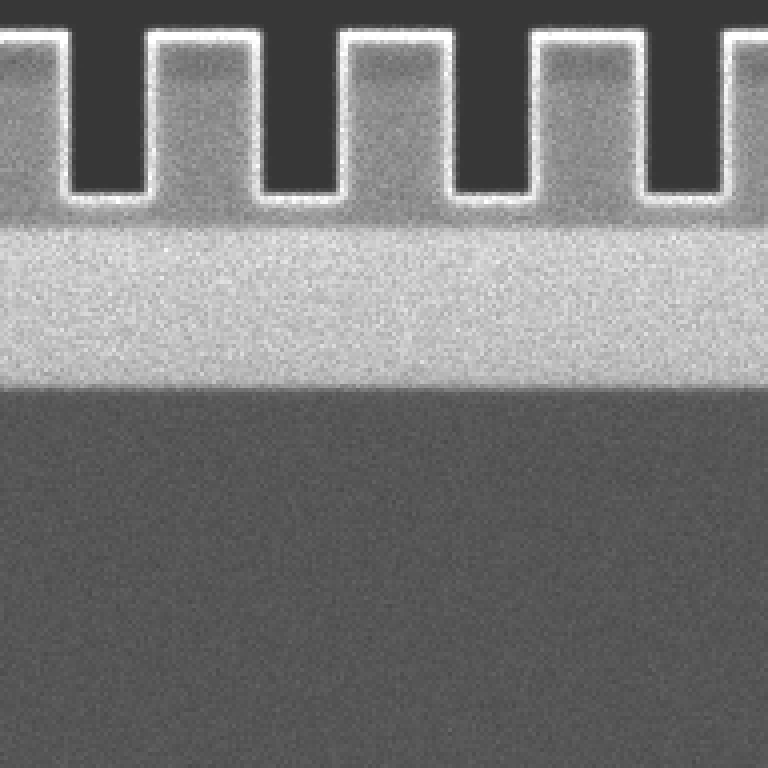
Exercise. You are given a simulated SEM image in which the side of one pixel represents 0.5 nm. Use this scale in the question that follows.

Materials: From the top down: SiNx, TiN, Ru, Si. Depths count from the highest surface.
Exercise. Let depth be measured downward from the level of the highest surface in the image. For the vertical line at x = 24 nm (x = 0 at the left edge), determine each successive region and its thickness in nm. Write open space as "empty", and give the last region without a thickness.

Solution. SiNx 24, TiN 74, Ru 80, Si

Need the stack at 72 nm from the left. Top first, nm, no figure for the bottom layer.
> empty 82, TiN 16, Ru 80, Si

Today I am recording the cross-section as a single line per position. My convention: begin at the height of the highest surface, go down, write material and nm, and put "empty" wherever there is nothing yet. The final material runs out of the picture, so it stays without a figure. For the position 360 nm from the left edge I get empty 82, TiN 16, Ru 80, Si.